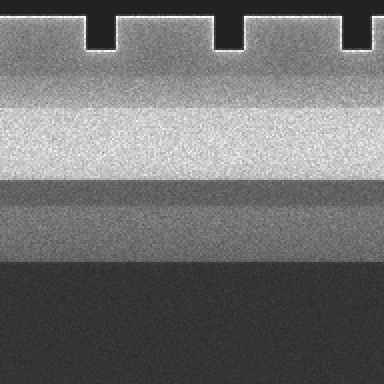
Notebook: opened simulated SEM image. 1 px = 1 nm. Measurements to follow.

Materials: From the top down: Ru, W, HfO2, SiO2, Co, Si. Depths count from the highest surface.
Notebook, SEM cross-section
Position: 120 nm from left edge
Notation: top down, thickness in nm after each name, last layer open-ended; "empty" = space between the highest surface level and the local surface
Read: Ru 60, W 32, HfO2 72, SiO2 26, Co 56, Si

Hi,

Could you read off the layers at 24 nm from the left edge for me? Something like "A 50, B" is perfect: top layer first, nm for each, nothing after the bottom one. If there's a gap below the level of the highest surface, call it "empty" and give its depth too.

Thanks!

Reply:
Ru 60, W 32, HfO2 72, SiO2 26, Co 56, Si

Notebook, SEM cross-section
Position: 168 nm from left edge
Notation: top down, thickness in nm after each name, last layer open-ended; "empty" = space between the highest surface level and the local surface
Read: Ru 60, W 32, HfO2 72, SiO2 26, Co 56, Si